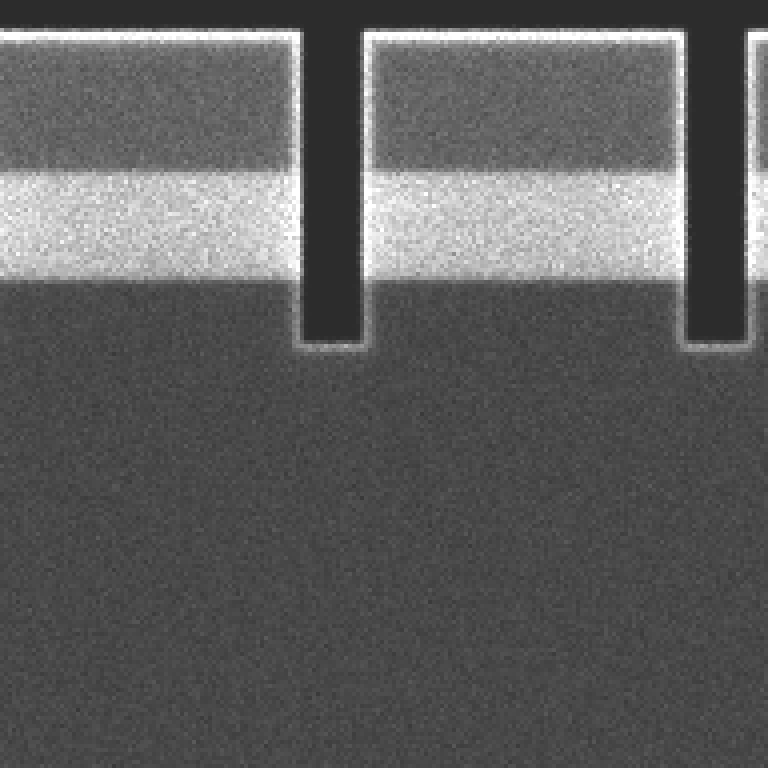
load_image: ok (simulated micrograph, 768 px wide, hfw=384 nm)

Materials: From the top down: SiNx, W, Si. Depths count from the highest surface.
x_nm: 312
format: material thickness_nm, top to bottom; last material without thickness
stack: SiNx 70, W 54, Si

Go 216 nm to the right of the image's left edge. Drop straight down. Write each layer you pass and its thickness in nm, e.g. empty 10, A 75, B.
SiNx 70, W 54, Si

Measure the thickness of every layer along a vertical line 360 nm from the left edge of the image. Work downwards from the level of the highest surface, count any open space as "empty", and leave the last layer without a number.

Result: empty 156, Si